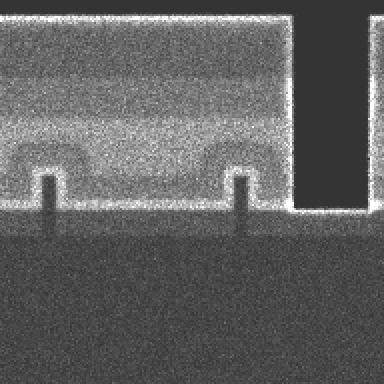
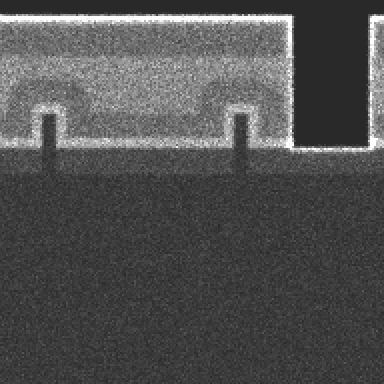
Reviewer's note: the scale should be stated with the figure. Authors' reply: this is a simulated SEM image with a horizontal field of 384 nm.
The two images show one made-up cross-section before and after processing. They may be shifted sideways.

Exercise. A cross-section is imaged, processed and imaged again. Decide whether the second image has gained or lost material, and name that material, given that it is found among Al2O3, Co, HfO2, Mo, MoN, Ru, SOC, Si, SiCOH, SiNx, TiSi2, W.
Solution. removed: SOC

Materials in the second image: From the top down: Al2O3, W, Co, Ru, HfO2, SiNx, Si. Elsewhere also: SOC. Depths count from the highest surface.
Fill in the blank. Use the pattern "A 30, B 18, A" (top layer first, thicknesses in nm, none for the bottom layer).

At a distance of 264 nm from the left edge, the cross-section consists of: Al2O3 40, W 24, Co 14, Ru 44, HfO2 10, SiNx 26, Si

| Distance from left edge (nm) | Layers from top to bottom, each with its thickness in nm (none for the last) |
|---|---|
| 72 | Al2O3 40, W 24, Co 14, Ru 44, HfO2 10, SiNx 26, Si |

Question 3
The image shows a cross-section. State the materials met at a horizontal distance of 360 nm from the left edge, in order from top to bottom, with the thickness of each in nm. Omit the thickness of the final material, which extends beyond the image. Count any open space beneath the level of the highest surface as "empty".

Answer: empty 132, SiNx 26, Si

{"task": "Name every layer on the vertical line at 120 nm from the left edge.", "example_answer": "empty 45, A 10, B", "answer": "Al2O3 40, W 58, Co 10, Ru 14, HfO2 10, SiNx 26, Si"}